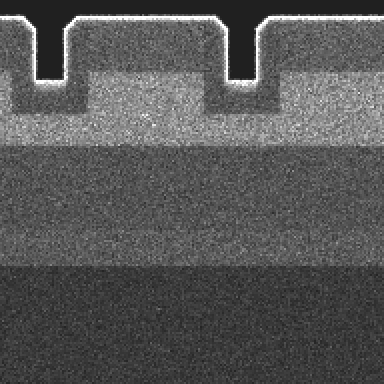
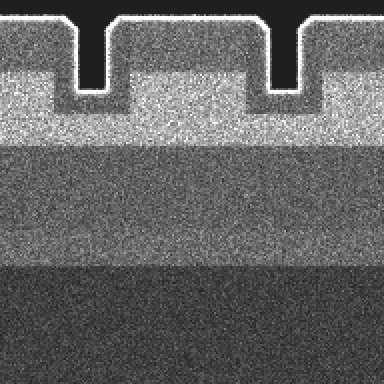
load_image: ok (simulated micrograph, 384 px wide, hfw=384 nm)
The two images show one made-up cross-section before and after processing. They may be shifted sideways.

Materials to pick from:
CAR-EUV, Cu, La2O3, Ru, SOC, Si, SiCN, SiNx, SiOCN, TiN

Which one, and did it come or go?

SOC - removed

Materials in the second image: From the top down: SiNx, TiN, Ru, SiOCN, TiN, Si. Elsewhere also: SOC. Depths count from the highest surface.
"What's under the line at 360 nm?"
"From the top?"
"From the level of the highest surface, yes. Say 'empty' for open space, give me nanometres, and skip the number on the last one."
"SiNx 10, TiN 46, Ru 74, SiOCN 84, TiN 36, Si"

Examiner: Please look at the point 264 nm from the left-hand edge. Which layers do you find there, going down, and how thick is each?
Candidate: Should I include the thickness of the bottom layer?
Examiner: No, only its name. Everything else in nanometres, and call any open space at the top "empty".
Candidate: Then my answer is empty 8, SiNx 90, Ru 32, SiOCN 84, TiN 36, Si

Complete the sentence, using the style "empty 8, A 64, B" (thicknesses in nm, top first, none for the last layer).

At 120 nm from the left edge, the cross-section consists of SiNx 98, Ru 32, SiOCN 84, TiN 36, Si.